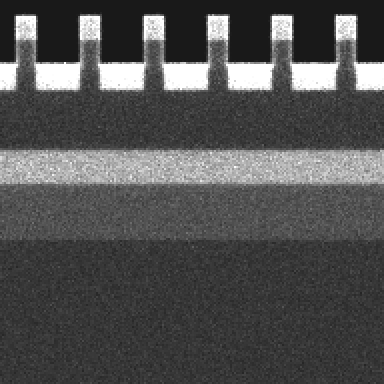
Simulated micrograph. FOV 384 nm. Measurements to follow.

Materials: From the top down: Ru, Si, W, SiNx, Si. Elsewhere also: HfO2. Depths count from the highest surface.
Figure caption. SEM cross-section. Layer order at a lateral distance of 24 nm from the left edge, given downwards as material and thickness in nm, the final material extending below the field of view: Ru 24, Si 110, W 34, SiNx 56, Si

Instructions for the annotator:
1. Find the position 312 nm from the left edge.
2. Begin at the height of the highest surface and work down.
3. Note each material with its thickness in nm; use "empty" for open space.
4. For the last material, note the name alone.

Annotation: empty 48, HfO2 26, Si 60, W 34, SiNx 56, Si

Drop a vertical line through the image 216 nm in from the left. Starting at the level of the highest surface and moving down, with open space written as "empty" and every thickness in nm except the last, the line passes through Ru 24, Si 110, W 34, SiNx 56, Si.